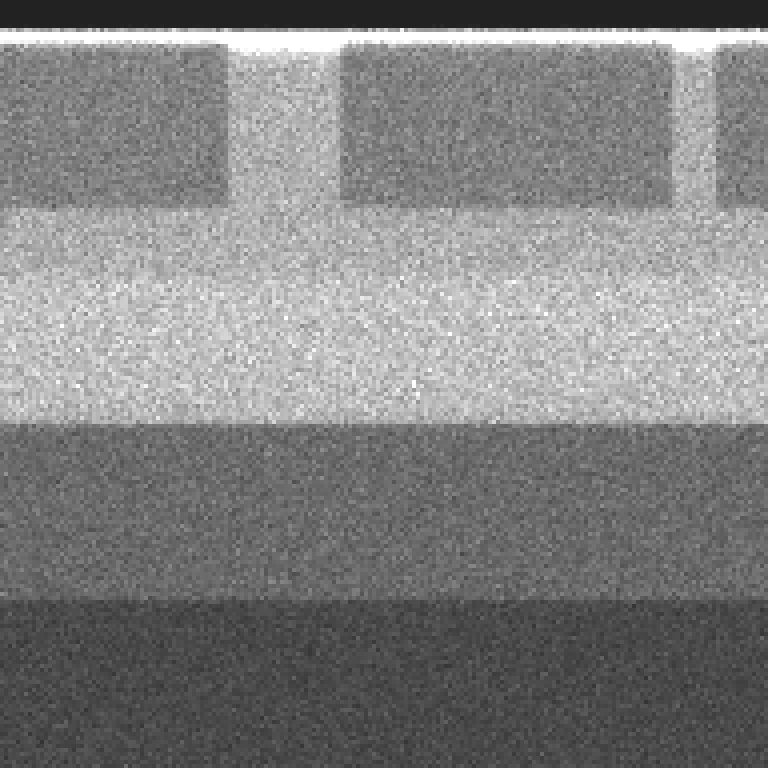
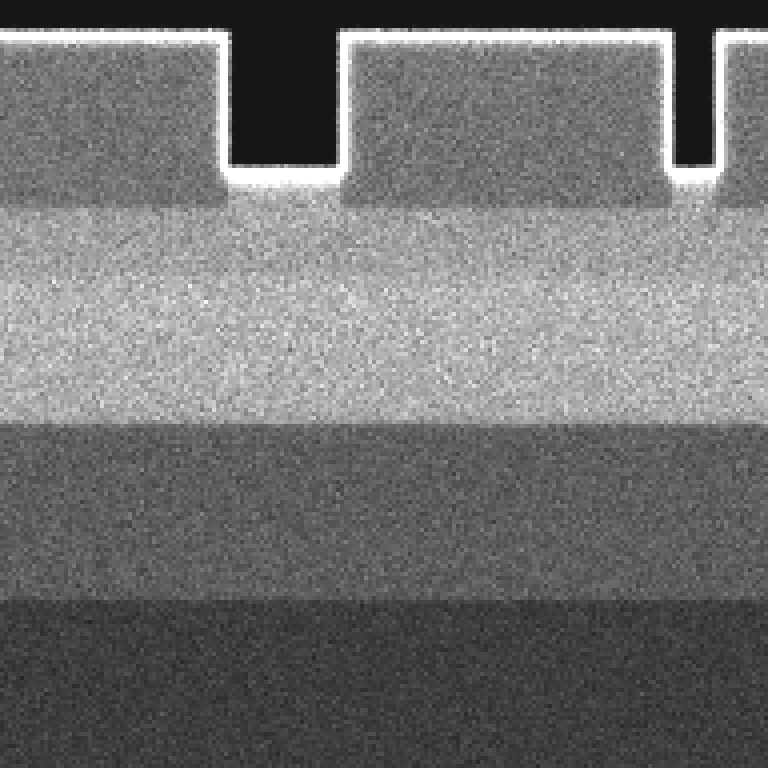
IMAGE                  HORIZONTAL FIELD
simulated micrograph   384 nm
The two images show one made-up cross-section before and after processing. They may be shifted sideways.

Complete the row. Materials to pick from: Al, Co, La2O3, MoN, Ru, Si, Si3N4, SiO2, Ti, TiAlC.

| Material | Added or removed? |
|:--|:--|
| SiO2 | removed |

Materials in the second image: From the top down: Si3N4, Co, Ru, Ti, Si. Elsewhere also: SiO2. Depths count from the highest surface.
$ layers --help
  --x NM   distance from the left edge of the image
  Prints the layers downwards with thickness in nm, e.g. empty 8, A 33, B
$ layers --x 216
Si3N4 88, Co 34, Ru 74, Ti 88, Si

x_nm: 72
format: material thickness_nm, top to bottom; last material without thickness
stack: Si3N4 88, Co 34, Ru 74, Ti 88, Si